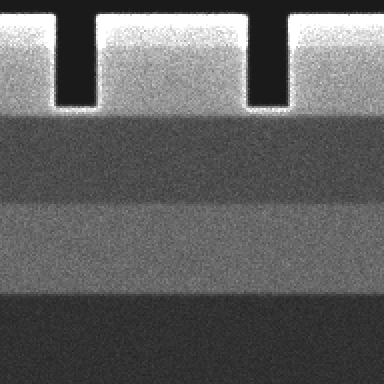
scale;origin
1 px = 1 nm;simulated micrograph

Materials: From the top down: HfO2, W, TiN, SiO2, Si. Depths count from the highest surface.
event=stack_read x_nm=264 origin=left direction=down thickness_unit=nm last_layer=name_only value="empty 92, W 8, TiN 88, SiO2 90, Si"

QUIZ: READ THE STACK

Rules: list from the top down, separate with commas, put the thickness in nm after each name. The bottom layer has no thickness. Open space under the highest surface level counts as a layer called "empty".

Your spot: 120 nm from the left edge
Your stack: HfO2 30, W 70, TiN 88, SiO2 90, Si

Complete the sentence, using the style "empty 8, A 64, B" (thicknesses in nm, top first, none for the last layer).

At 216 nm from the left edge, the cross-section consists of HfO2 30, W 70, TiN 88, SiO2 90, Si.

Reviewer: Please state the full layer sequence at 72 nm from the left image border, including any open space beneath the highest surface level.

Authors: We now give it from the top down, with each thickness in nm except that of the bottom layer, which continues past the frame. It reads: empty 92, W 8, TiN 88, SiO2 90, Si